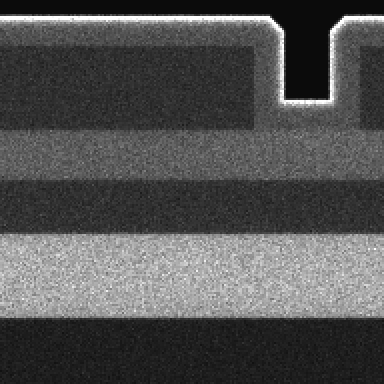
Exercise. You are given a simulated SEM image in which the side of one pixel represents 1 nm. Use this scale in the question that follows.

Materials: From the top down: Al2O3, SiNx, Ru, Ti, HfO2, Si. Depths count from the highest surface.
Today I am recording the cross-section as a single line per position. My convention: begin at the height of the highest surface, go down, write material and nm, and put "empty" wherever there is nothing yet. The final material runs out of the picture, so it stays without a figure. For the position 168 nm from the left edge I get Al2O3 30, SiNx 84, Ru 50, Ti 54, HfO2 84, Si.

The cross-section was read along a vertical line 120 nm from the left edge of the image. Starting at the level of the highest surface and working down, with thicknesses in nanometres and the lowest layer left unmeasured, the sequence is Al2O3 30, SiNx 84, Ru 50, Ti 54, HfO2 84, Si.